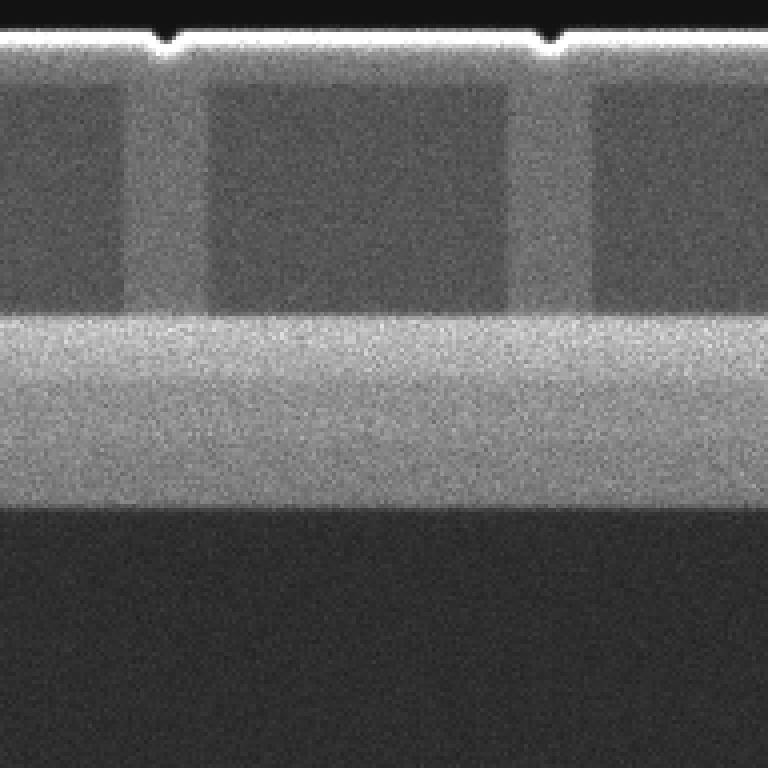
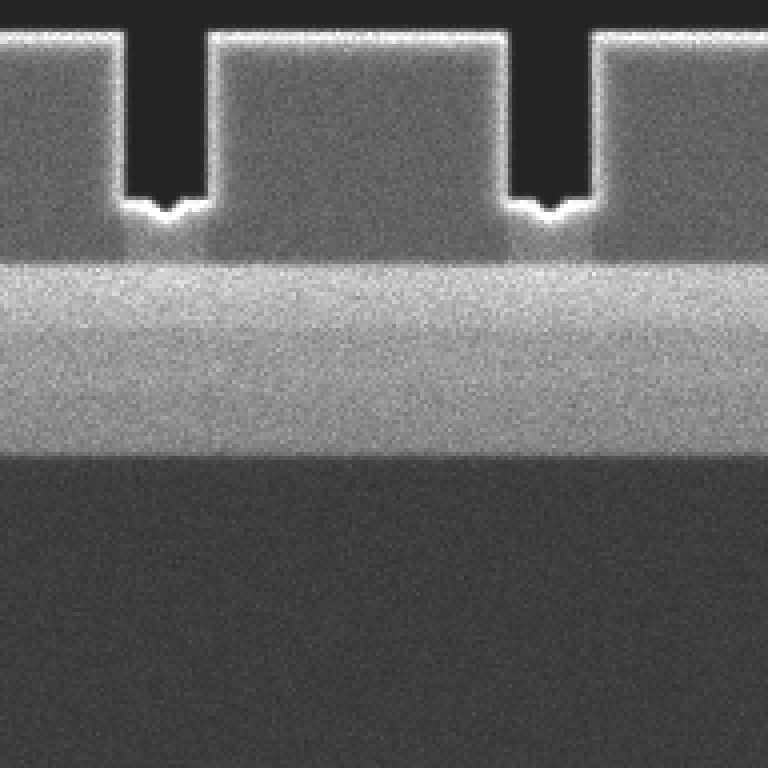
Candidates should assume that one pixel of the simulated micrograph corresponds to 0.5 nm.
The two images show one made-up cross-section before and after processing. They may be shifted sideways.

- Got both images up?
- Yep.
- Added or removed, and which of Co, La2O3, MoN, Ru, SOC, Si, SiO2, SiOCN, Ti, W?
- removed, SiO2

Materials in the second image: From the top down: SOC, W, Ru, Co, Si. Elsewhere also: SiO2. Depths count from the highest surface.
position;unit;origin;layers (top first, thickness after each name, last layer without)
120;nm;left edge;SOC 116, W 32, Ru 30, Co 34, Si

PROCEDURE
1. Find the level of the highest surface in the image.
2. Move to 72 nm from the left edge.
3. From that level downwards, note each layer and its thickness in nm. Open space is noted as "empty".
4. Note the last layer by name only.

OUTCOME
empty 84, SiO2 32, W 32, Ru 30, Co 34, Si